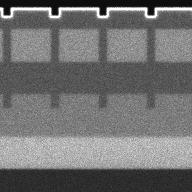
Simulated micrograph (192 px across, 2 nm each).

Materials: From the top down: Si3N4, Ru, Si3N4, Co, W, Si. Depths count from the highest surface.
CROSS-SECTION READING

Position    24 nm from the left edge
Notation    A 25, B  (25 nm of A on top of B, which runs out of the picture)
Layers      Si3N4 42, Ru 66, Si3N4 64, Co 86, W 64, Si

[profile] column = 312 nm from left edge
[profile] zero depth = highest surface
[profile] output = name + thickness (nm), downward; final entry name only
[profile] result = Si3N4 42, Ru 66, Si3N4 64, Co 86, W 64, Si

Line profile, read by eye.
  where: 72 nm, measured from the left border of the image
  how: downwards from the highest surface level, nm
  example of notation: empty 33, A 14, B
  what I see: Si3N4 42, Ru 66, Si3N4 64, Co 86, W 64, Si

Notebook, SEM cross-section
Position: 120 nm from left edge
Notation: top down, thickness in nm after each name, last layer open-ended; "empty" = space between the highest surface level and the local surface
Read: Si3N4 42, Ru 66, Si3N4 64, Co 86, W 64, Si